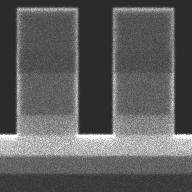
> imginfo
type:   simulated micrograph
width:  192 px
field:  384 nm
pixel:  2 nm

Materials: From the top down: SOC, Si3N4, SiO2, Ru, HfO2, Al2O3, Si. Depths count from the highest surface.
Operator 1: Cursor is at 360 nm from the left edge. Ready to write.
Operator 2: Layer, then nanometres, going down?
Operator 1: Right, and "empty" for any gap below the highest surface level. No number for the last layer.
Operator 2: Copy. empty 254, HfO2 42, Al2O3 36, Si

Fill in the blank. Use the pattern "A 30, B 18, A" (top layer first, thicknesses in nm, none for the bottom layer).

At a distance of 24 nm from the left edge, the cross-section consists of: empty 254, HfO2 42, Al2O3 36, Si